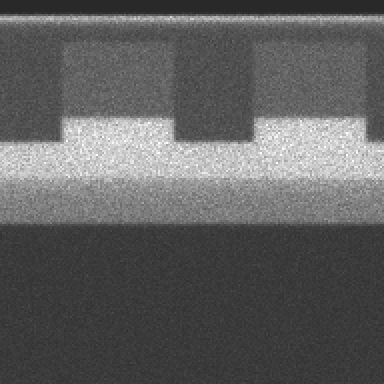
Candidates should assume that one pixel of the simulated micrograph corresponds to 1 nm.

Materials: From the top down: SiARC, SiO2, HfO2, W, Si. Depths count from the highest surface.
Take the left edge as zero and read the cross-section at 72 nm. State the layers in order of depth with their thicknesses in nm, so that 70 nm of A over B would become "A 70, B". SiARC 26, SiO2 76, HfO2 60, W 46, Si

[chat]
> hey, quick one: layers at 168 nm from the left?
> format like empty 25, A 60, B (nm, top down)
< SiARC 26, SiO2 76, HfO2 60, W 46, Si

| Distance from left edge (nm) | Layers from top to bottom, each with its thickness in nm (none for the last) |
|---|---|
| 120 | SiARC 26, SiO2 76, HfO2 60, W 46, Si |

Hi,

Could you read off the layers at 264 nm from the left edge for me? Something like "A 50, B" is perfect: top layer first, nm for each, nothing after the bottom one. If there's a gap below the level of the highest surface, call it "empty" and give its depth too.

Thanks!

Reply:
SiARC 26, SiO2 76, HfO2 60, W 46, Si